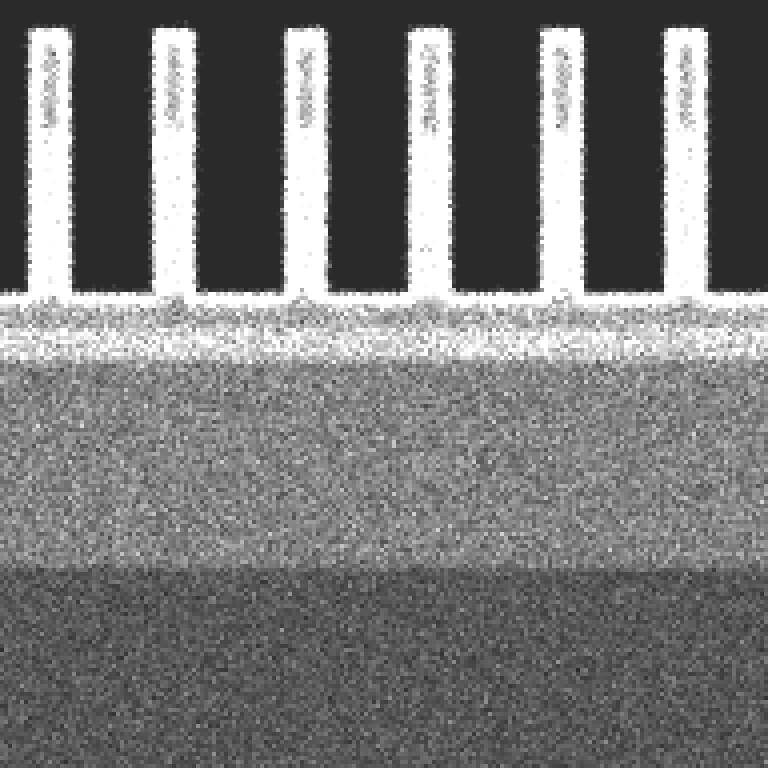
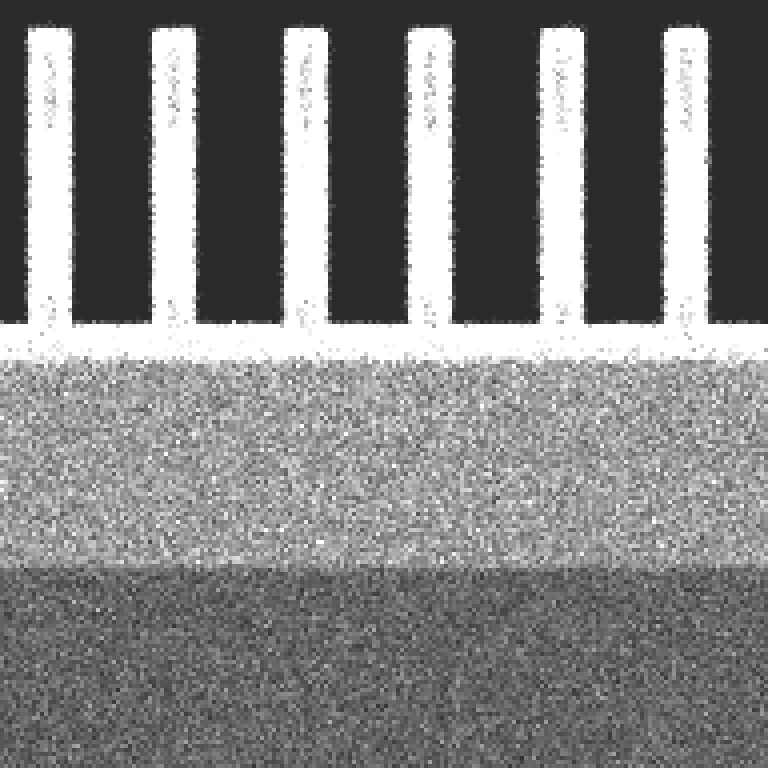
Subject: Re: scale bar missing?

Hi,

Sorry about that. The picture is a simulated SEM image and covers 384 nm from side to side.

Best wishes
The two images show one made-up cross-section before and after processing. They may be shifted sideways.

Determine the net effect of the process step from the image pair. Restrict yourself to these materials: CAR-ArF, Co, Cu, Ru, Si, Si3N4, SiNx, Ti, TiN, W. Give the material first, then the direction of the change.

TiN: removed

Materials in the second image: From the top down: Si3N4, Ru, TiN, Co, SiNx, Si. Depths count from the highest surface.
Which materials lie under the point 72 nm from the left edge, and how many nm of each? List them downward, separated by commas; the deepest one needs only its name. empty 148, Co 16, SiNx 104, Si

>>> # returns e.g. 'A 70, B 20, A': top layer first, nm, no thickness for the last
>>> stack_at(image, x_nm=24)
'Si3N4 50, Ru 82, TiN 16, Co 16, SiNx 104, Si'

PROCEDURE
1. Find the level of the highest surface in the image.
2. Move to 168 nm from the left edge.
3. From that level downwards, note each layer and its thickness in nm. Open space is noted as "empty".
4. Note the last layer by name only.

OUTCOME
empty 148, Co 16, SiNx 104, Si